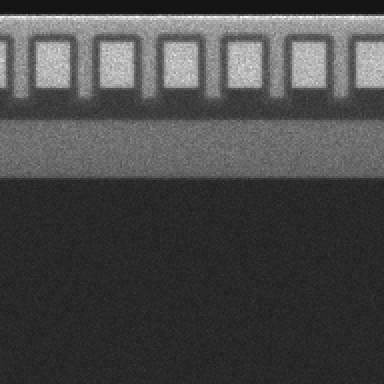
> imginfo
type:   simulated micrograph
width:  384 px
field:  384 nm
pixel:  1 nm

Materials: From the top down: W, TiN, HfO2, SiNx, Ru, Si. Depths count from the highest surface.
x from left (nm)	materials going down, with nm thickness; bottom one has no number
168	W 18, TiN 8, HfO2 46, SiNx 32, Ru 58, Si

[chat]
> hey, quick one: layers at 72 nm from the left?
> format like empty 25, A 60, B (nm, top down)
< W 18, TiN 72, SiNx 14, Ru 58, Si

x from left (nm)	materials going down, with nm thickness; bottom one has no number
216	W 82, TiN 8, SiNx 14, Ru 58, Si